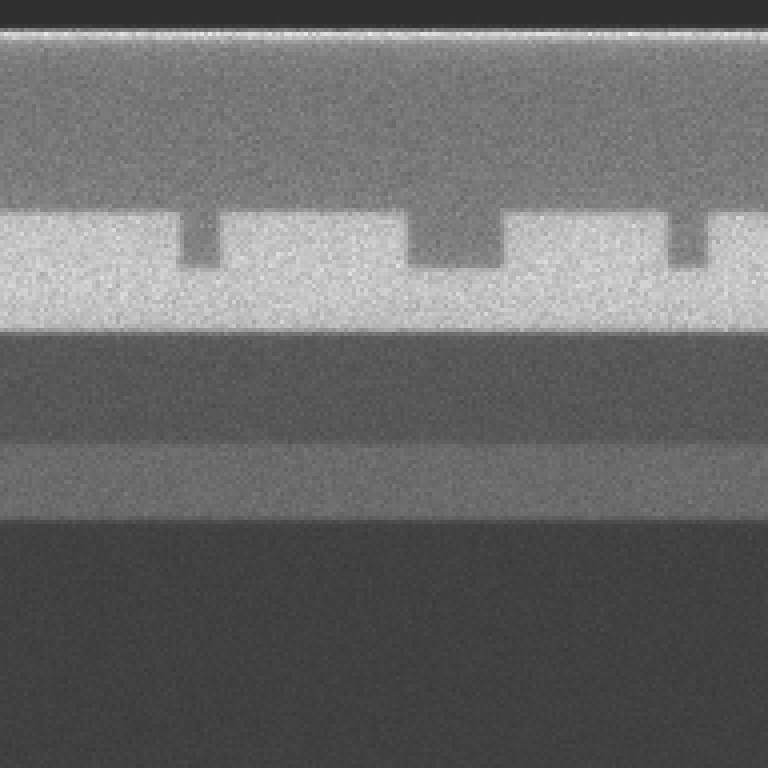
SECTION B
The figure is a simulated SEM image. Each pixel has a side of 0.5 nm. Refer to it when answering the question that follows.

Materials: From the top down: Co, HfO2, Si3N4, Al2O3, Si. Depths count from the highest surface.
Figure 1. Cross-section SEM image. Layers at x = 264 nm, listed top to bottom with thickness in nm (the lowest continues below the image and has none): Co 90, HfO2 60, Si3N4 56, Al2O3 38, Si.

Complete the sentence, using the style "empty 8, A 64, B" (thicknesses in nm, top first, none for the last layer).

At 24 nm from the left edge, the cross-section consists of Co 90, HfO2 60, Si3N4 56, Al2O3 38, Si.